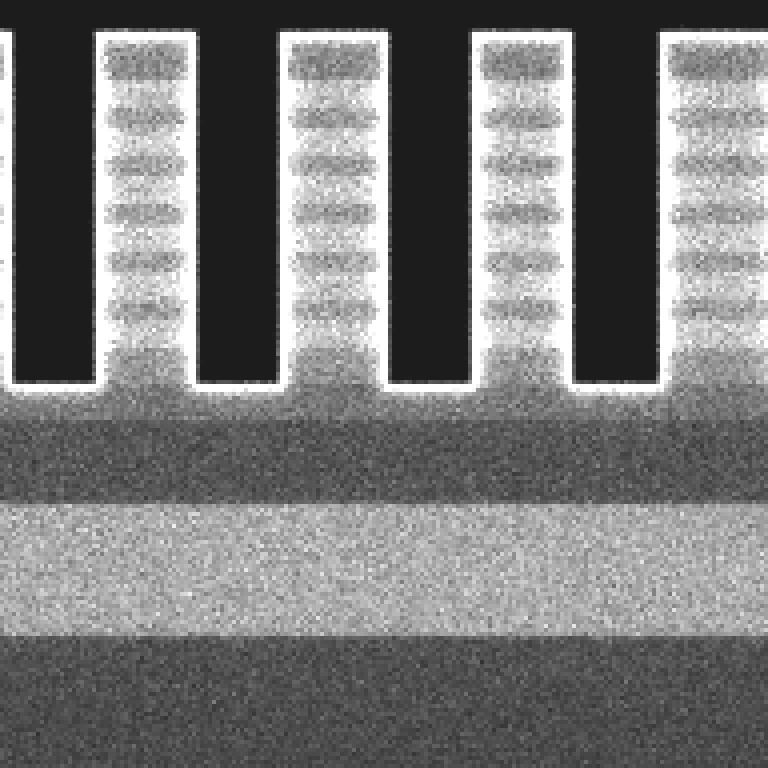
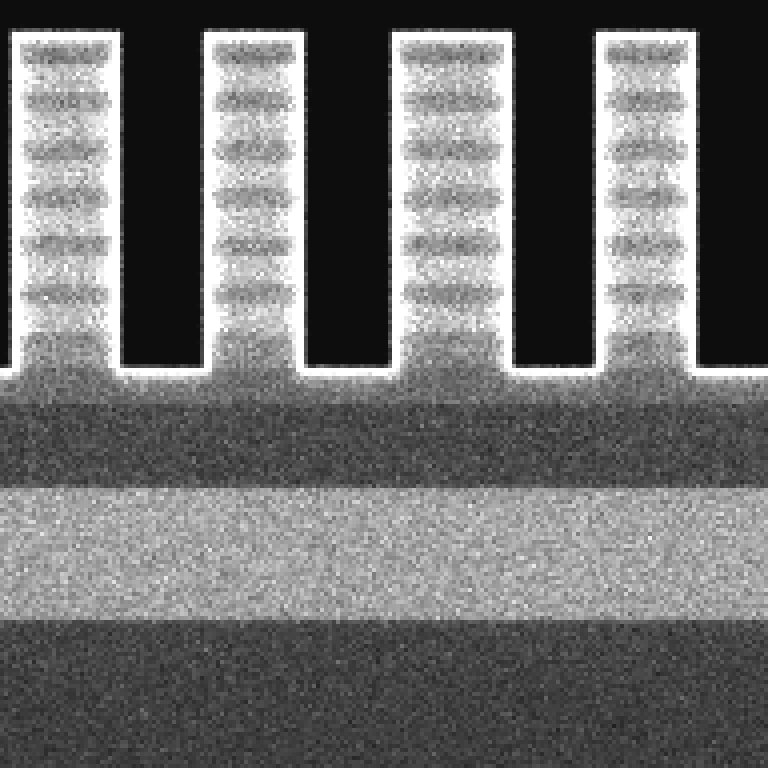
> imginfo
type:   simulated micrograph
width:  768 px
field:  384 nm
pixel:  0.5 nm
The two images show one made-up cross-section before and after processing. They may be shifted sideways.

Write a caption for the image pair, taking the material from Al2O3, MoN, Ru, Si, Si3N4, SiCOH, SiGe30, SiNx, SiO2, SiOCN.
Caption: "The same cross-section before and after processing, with SiNx removed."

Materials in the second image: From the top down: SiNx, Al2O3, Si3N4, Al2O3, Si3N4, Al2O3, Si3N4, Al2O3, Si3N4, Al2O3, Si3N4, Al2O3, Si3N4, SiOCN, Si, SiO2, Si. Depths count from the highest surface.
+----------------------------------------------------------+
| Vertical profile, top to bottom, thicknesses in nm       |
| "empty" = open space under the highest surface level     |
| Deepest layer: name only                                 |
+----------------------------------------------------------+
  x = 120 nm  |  SiNx 16, Al2O3 14, Si3N4 10, Al2O3 14, Si3N4 10, Al2O3 14, Si3N4 10, Al2O3 14, Si3N4 10, Al2O3 14, Si3N4 10, Al2O3 14, Si3N4 18, SiOCN 18, Si 42, SiO2 66, Si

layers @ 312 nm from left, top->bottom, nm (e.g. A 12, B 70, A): SiNx 16, Al2O3 14, Si3N4 10, Al2O3 14, Si3N4 10, Al2O3 14, Si3N4 10, Al2O3 14, Si3N4 10, Al2O3 14, Si3N4 10, Al2O3 14, Si3N4 18, SiOCN 18, Si 42, SiO2 66, Si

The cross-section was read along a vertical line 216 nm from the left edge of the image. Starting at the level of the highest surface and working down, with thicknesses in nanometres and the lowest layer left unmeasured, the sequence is SiNx 16, Al2O3 14, Si3N4 10, Al2O3 14, Si3N4 10, Al2O3 14, Si3N4 10, Al2O3 14, Si3N4 10, Al2O3 14, Si3N4 10, Al2O3 14, Si3N4 18, SiOCN 18, Si 42, SiO2 66, Si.